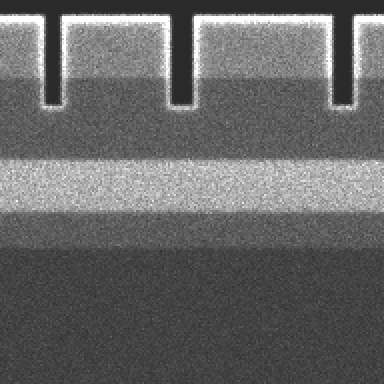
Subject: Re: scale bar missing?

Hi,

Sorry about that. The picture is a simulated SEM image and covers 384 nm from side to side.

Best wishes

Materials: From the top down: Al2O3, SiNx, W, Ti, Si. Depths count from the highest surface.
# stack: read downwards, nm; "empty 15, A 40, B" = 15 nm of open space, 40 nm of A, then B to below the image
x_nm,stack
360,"Al2O3 62, SiNx 82, W 52, Ti 36, Si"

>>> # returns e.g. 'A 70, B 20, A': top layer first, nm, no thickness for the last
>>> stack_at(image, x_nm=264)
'Al2O3 62, SiNx 82, W 52, Ti 36, Si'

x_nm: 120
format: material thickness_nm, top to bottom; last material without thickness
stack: Al2O3 62, SiNx 82, W 52, Ti 36, Si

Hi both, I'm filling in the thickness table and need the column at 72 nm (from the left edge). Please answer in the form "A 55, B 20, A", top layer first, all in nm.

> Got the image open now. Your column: Al2O3 62, SiNx 82, W 52, Ti 36, Si